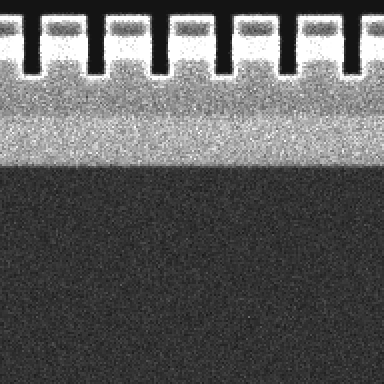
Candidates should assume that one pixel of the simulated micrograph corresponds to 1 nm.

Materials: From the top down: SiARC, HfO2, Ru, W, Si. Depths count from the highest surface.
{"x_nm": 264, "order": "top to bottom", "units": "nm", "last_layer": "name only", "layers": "SiARC 20, HfO2 24, Ru 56, W 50, Si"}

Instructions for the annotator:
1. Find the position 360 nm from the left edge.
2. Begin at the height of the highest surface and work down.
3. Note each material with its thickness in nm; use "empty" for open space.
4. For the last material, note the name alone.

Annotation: empty 60, Ru 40, W 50, Si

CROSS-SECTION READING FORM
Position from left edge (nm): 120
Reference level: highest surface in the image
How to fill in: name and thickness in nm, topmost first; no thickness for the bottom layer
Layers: SiARC 20, HfO2 24, Ru 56, W 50, Si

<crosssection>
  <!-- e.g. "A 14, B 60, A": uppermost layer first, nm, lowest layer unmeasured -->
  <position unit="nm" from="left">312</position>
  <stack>SiARC 20, HfO2 24, Ru 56, W 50, Si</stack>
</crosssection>